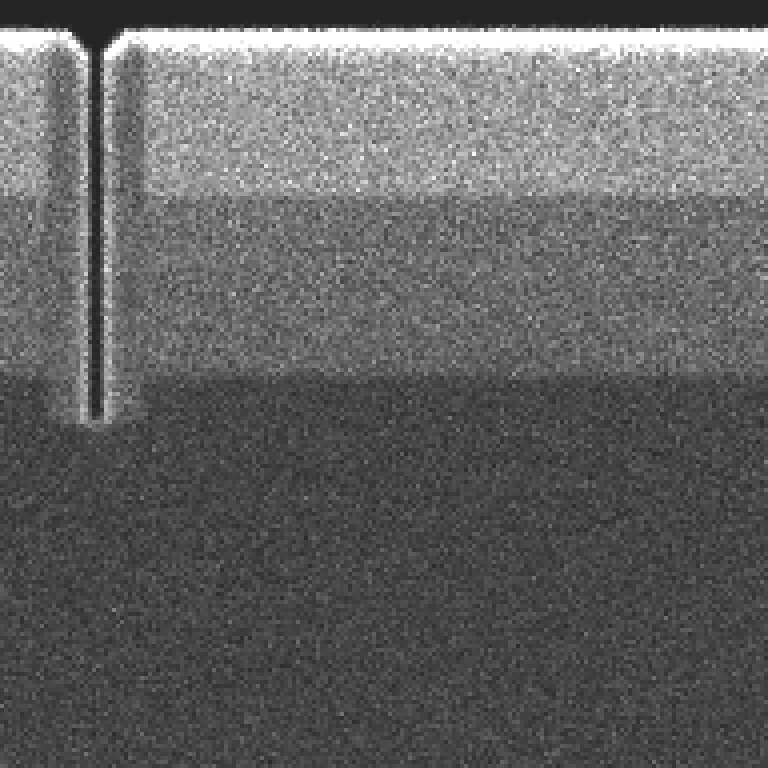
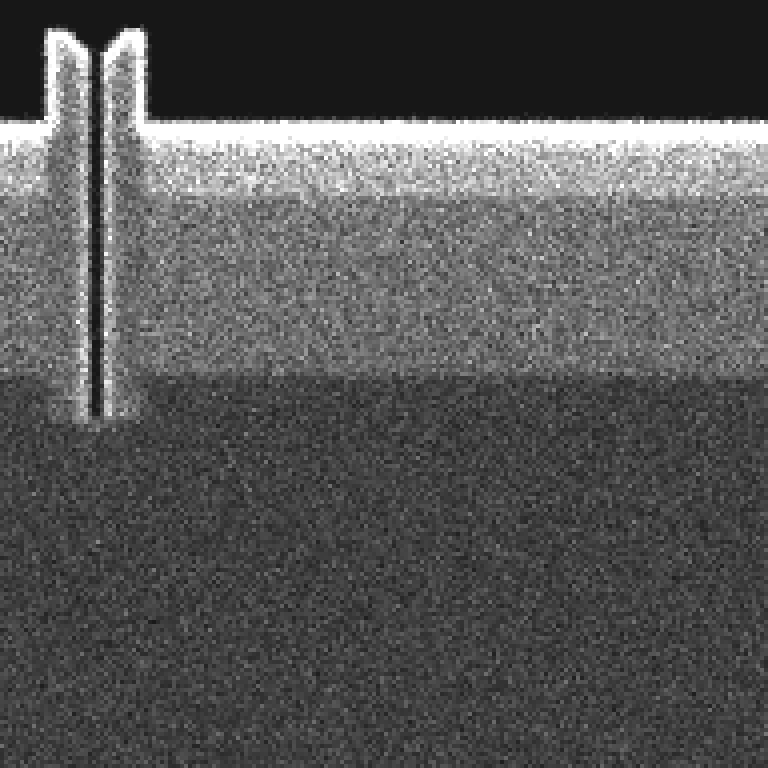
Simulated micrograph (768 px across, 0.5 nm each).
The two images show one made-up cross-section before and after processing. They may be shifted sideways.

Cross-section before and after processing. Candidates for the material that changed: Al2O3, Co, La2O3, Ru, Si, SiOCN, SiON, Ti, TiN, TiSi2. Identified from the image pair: Al2O3 (removed).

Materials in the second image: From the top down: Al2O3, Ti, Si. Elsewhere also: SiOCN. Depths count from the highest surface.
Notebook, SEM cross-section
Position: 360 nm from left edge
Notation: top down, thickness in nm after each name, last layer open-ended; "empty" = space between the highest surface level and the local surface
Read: empty 46, Al2O3 36, Ti 90, Si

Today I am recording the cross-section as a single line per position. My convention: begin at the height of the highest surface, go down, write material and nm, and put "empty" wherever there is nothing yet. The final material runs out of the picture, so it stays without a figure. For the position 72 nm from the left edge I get empty 46, Al2O3 36, Ti 90, Si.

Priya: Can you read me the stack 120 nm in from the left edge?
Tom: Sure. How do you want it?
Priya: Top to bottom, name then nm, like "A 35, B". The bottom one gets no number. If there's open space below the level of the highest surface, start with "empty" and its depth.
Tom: empty 46, Al2O3 36, Ti 90, Si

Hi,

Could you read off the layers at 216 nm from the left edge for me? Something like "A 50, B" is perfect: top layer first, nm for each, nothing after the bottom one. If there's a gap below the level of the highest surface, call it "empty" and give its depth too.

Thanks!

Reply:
empty 46, Al2O3 36, Ti 90, Si